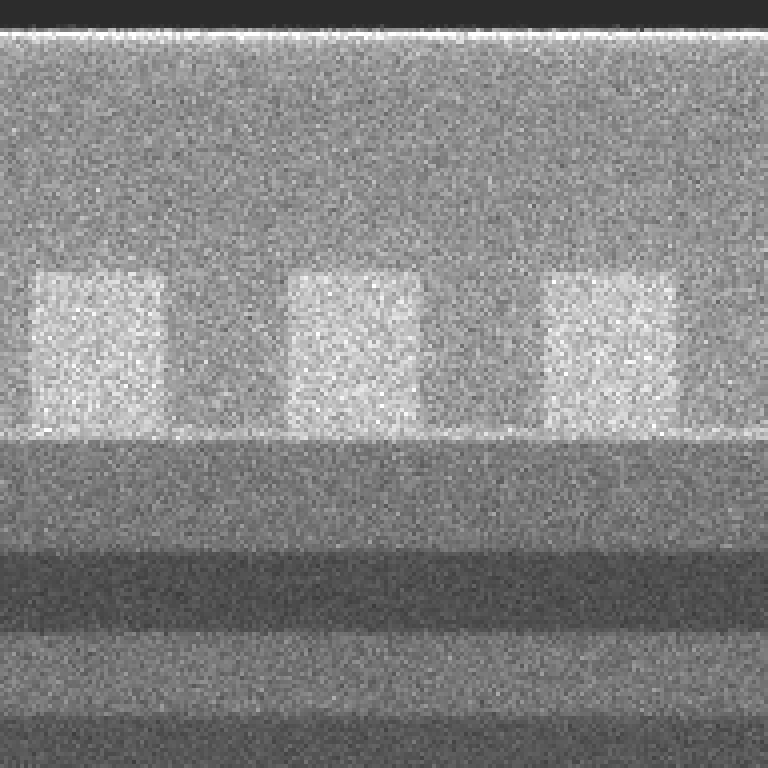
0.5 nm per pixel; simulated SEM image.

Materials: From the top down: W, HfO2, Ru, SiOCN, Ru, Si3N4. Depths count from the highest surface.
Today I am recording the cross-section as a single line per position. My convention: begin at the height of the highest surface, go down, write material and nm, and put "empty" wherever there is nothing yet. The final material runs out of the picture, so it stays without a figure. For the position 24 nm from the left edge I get W 120, HfO2 84, Ru 56, SiOCN 40, Ru 42, Si3N4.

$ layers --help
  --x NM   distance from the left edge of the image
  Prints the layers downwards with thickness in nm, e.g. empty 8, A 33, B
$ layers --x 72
W 120, HfO2 84, Ru 56, SiOCN 40, Ru 42, Si3N4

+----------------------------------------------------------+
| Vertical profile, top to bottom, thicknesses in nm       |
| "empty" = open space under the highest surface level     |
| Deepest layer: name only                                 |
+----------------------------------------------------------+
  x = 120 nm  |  W 198, HfO2 6, Ru 56, SiOCN 40, Ru 42, Si3N4